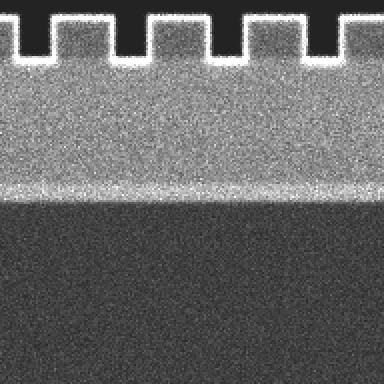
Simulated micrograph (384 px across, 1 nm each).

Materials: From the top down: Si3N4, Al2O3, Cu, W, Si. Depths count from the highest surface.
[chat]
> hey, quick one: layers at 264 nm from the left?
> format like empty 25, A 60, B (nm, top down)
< Si3N4 42, Al2O3 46, Cu 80, W 18, Si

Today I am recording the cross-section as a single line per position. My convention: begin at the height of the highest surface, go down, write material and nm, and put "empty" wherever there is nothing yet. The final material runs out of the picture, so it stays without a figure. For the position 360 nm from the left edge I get Si3N4 42, Al2O3 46, Cu 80, W 18, Si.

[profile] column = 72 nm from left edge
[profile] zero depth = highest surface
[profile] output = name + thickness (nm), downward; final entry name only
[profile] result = Si3N4 42, Al2O3 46, Cu 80, W 18, Si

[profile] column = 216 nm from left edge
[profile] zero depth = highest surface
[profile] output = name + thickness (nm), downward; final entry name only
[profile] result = empty 42, Al2O3 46, Cu 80, W 18, Si